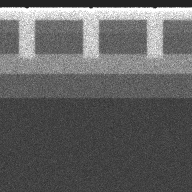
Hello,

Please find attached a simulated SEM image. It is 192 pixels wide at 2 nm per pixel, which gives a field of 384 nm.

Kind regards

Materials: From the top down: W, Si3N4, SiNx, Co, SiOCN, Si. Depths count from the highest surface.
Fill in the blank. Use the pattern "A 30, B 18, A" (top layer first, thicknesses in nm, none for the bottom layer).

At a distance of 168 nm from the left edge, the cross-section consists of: W 100, Co 32, SiOCN 48, Si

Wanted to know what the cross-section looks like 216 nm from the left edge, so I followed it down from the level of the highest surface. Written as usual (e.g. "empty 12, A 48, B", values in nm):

W 24, Si3N4 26, SiNx 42, Co 40, SiOCN 48, Si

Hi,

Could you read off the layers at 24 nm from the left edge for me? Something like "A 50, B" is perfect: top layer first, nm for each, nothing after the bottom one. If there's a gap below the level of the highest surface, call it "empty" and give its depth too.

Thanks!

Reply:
W 24, Si3N4 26, SiNx 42, Co 40, SiOCN 48, Si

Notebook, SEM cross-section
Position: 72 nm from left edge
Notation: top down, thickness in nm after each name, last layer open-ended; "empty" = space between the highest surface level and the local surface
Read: W 24, Si3N4 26, SiNx 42, Co 40, SiOCN 48, Si